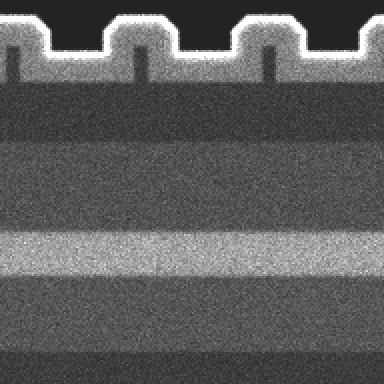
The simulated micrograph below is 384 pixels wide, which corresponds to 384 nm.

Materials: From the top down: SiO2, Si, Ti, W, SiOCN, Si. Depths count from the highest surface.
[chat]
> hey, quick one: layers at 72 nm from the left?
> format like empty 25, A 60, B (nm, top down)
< empty 36, SiO2 30, Si 60, Ti 90, W 44, SiOCN 76, Si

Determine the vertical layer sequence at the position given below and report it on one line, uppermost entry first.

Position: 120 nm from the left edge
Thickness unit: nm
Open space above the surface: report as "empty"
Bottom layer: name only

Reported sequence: SiO2 66, Si 60, Ti 90, W 44, SiOCN 76, Si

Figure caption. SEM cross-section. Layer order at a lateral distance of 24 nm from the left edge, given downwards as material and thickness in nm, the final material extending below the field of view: SiO2 66, Si 60, Ti 90, W 44, SiOCN 76, Si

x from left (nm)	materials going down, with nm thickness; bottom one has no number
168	empty 6, SiO2 60, Si 60, Ti 90, W 44, SiOCN 76, Si